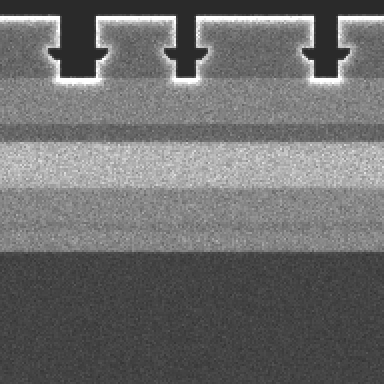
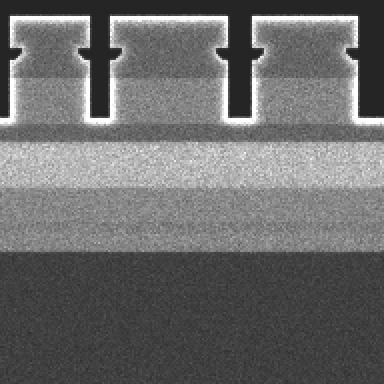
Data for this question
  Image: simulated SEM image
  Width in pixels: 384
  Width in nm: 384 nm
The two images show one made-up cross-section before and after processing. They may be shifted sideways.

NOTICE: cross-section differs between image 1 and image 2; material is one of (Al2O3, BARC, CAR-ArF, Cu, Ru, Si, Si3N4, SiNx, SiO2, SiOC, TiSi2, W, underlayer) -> removed: SiO2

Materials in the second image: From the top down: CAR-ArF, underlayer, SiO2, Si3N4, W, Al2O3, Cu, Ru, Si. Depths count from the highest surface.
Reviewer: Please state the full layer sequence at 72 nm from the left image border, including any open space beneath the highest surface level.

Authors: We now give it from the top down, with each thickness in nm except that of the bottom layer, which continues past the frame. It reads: CAR-ArF 32, underlayer 30, SiO2 46, Si3N4 18, W 46, Al2O3 34, Cu 10, Ru 20, Si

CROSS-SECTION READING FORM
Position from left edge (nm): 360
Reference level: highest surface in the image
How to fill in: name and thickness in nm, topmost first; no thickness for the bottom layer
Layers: empty 102, SiO2 6, Si3N4 18, W 46, Al2O3 34, Cu 10, Ru 20, Si